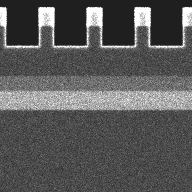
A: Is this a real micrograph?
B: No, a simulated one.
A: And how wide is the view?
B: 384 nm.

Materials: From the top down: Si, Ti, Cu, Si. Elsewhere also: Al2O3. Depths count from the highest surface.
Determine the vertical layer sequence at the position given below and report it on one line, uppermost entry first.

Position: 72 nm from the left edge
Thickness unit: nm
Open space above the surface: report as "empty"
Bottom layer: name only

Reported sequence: empty 76, Si 60, Ti 30, Cu 38, Si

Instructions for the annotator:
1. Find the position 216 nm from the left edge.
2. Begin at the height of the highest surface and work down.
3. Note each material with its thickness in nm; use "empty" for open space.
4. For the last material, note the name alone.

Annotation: empty 76, Si 60, Ti 30, Cu 38, Si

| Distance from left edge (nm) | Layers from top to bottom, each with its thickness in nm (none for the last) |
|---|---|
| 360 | empty 76, Si 60, Ti 30, Cu 38, Si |